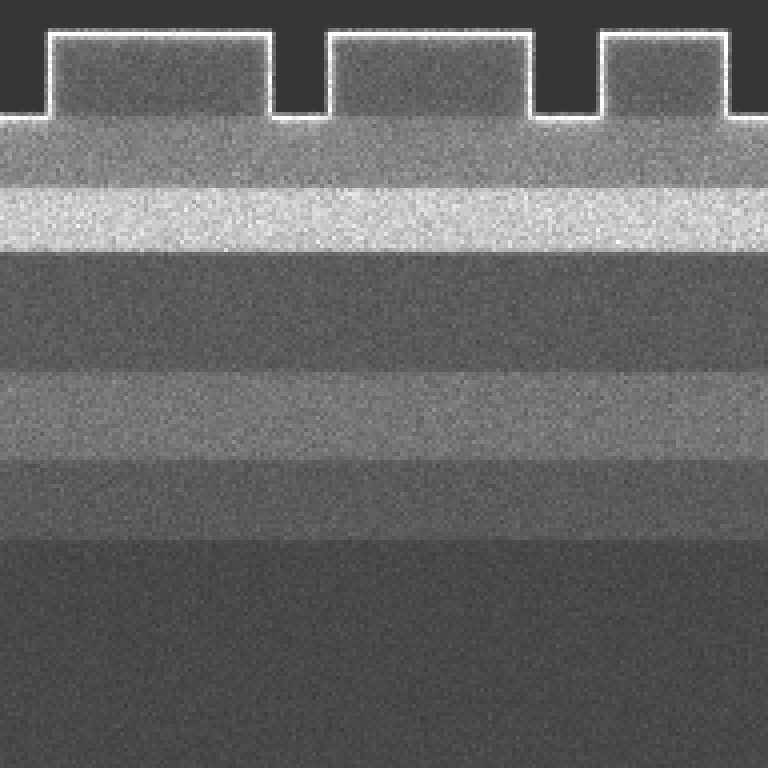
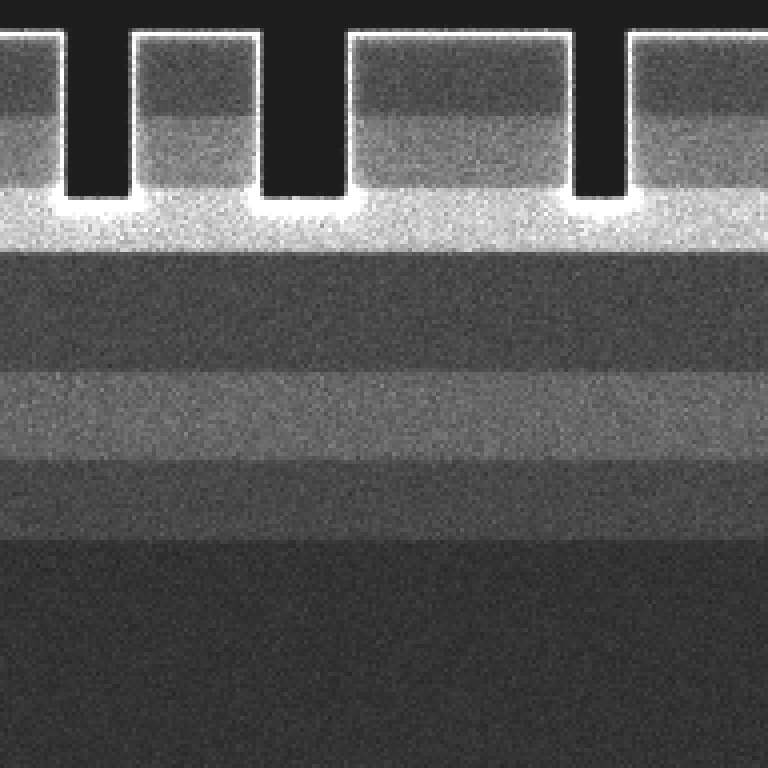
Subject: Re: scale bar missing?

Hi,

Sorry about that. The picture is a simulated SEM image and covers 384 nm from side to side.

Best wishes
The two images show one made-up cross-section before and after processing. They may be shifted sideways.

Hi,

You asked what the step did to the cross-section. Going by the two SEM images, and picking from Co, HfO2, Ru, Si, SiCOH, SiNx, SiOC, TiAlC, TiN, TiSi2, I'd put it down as HfO2 and Ru, removed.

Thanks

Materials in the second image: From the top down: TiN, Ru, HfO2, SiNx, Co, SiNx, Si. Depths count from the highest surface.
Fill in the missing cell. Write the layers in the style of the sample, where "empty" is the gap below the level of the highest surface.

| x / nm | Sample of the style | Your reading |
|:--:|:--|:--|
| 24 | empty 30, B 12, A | TiN 42, Ru 36, HfO2 32, SiNx 60, Co 44, SiNx 40, Si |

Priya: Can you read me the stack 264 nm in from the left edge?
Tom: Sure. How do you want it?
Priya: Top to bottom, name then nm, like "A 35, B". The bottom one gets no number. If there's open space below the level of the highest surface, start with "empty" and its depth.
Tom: TiN 42, Ru 36, HfO2 32, SiNx 60, Co 44, SiNx 40, Si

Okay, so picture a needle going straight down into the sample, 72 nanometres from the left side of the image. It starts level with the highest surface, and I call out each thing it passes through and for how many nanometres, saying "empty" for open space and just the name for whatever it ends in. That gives TiN 42, Ru 36, HfO2 32, SiNx 60, Co 44, SiNx 40, Si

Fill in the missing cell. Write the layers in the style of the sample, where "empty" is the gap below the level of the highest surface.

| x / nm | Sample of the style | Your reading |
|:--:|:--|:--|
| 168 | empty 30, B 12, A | empty 84, HfO2 26, SiNx 60, Co 44, SiNx 40, Si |